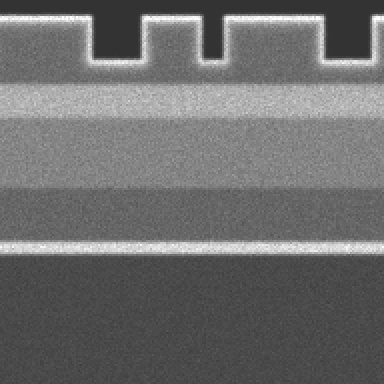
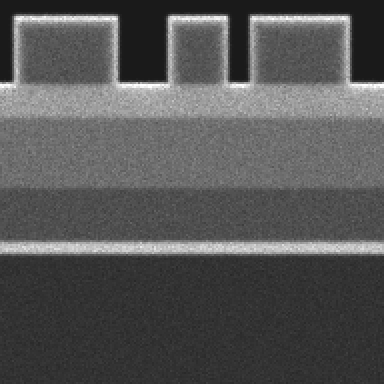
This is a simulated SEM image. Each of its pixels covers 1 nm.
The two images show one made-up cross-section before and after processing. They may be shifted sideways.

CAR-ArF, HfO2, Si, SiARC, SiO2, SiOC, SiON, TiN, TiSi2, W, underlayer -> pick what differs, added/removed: underlayer removed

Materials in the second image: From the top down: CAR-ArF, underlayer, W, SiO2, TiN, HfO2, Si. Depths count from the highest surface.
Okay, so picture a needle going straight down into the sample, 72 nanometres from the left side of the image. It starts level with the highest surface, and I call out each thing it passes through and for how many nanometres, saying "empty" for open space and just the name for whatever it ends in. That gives CAR-ArF 44, underlayer 24, W 34, SiO2 70, TiN 54, HfO2 12, Si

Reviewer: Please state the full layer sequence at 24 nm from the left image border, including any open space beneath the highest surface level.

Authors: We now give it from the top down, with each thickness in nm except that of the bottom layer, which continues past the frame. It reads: CAR-ArF 44, underlayer 24, W 34, SiO2 70, TiN 54, HfO2 12, Si